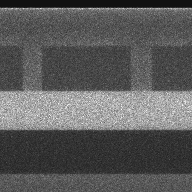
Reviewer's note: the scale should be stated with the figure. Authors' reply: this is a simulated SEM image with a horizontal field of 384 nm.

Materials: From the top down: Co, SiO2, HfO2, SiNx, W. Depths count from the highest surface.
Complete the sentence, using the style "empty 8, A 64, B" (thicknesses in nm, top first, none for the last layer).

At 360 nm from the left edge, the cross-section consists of Co 76, SiO2 90, HfO2 78, SiNx 88, W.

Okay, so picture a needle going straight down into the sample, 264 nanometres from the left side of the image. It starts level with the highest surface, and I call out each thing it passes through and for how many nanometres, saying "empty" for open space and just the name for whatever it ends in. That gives Co 166, HfO2 78, SiNx 88, W